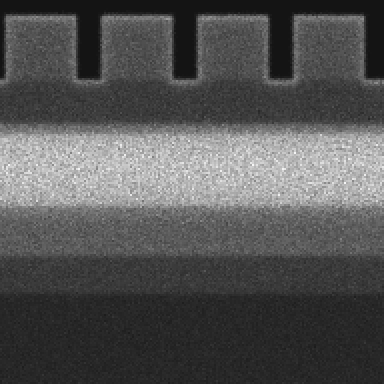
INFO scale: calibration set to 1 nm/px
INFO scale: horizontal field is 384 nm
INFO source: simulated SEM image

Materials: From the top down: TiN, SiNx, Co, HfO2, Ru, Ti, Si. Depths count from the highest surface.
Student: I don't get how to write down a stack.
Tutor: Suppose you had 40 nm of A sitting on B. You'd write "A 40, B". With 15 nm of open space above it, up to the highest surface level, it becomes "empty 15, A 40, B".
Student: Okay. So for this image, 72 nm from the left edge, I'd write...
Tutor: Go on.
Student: TiN 64, SiNx 44, Co 10, HfO2 72, Ru 50, Ti 38, Si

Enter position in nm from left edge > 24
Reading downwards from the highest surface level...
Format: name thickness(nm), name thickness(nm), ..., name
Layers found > TiN 64, SiNx 44, Co 10, HfO2 72, Ru 50, Ti 38, Si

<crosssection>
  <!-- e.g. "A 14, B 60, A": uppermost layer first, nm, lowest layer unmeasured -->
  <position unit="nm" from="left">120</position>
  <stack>TiN 64, SiNx 44, Co 10, HfO2 72, Ru 50, Ti 38, Si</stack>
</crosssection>